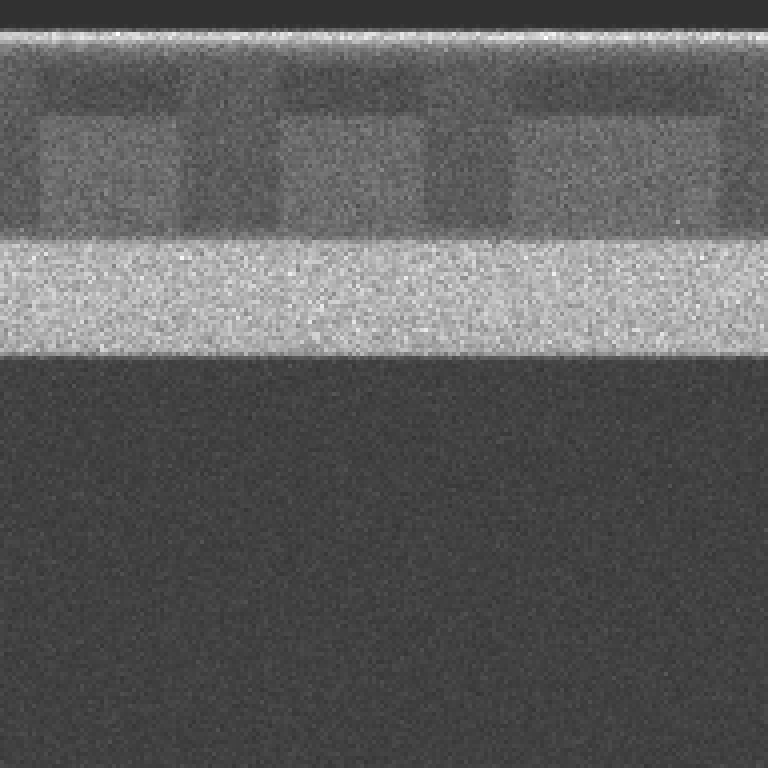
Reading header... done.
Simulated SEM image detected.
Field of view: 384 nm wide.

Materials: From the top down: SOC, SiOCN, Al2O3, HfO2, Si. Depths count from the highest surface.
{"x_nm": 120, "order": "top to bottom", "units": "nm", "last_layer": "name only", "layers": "SOC 98, Al2O3 6, HfO2 58, Si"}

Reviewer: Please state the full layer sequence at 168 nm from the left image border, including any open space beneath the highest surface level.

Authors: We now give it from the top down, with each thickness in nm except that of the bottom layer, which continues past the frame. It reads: SOC 16, SiOCN 26, Al2O3 62, HfO2 58, Si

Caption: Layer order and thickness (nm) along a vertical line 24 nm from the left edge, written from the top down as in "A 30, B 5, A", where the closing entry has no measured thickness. SOC 16, SiOCN 26, Al2O3 62, HfO2 58, Si